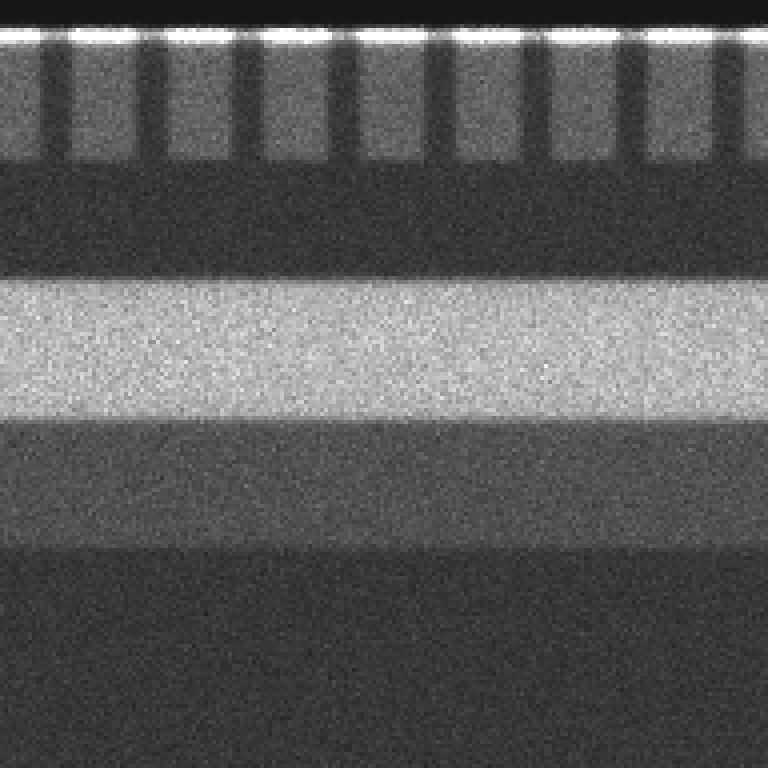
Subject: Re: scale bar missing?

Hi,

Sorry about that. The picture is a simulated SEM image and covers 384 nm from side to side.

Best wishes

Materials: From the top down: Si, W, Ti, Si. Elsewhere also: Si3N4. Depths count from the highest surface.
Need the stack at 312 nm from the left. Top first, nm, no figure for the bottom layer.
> Si 124, W 70, Ti 64, Si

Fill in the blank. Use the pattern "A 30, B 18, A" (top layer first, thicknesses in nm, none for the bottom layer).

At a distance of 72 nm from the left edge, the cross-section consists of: Si 124, W 70, Ti 64, Si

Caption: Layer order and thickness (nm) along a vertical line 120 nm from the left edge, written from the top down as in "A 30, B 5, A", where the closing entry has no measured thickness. Si 124, W 70, Ti 64, Si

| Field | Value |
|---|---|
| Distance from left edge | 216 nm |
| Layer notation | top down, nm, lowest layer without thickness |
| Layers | Si 124, W 70, Ti 64, Si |